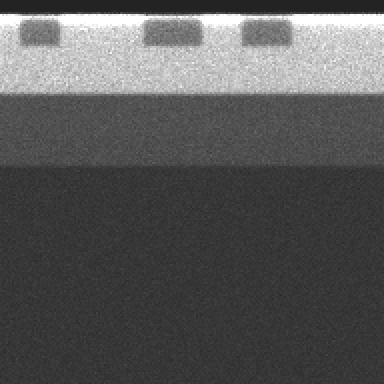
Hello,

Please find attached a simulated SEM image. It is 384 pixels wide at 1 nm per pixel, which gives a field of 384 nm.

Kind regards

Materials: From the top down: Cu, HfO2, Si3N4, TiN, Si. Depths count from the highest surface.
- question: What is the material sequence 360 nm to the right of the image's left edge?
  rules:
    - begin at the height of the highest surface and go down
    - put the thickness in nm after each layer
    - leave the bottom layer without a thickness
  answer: HfO2 78, Si3N4 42, TiN 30, Si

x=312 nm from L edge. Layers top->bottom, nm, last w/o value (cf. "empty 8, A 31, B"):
HfO2 78, Si3N4 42, TiN 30, Si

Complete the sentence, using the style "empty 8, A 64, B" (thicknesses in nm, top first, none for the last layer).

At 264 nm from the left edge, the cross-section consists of Cu 30, HfO2 48, Si3N4 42, TiN 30, Si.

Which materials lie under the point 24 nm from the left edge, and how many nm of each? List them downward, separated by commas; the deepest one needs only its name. Cu 30, HfO2 48, Si3N4 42, TiN 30, Si